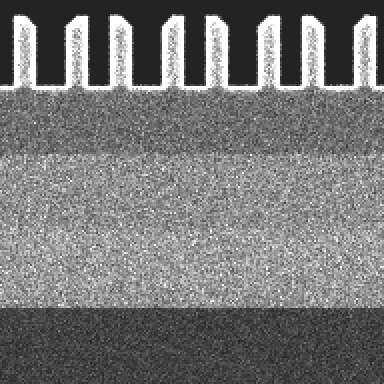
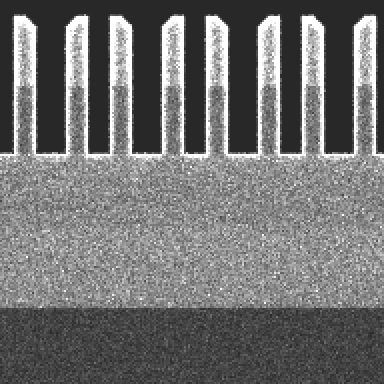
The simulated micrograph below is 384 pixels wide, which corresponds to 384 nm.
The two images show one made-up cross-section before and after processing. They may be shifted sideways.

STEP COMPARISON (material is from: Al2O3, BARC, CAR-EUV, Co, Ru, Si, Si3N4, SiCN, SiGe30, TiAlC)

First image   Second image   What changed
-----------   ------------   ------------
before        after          Si3N4, removed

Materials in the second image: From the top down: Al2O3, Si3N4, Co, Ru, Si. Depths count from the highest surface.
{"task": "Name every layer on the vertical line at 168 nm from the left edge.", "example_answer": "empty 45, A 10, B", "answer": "empty 4, Al2O3 66, Si3N4 68, Co 74, Ru 80, Si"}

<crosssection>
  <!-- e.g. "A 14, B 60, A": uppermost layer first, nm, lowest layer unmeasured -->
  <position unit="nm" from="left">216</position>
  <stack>Al2O3 70, Si3N4 68, Co 74, Ru 80, Si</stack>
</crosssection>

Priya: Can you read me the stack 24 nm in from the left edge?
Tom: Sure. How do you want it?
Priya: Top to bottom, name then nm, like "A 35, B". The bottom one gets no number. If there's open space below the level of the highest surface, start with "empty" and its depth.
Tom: Al2O3 70, Si3N4 68, Co 74, Ru 80, Si